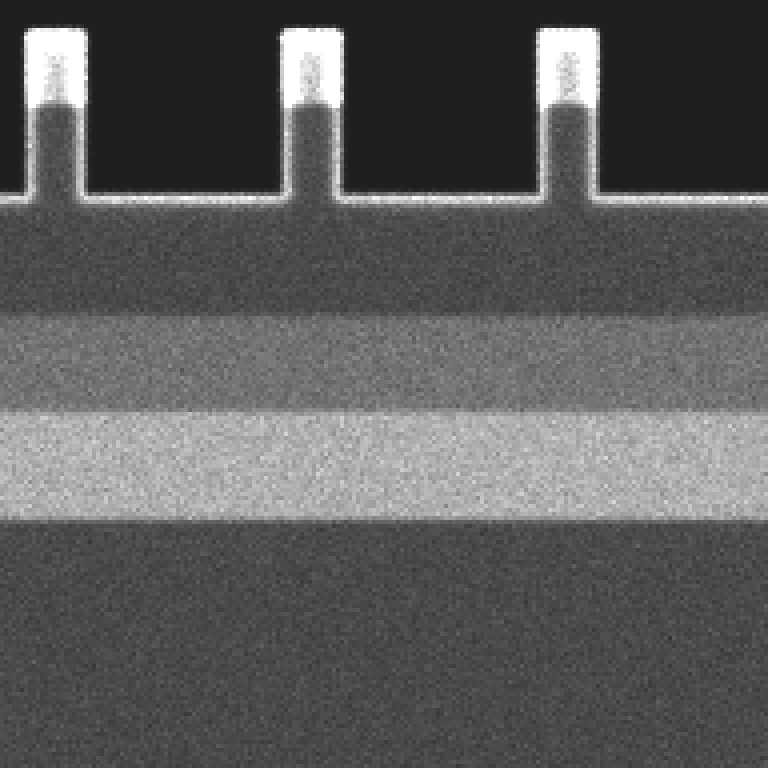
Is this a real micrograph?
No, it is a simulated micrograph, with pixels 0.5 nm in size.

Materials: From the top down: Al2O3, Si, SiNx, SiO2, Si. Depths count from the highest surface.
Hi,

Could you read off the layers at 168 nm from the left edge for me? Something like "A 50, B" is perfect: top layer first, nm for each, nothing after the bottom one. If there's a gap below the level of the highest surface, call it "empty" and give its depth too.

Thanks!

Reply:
Al2O3 36, Si 106, SiNx 48, SiO2 54, Si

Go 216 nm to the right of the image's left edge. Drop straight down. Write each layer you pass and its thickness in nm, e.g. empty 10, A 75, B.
empty 82, Si 60, SiNx 48, SiO2 54, Si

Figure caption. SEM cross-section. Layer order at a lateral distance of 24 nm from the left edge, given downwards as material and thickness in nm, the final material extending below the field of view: Al2O3 36, Si 106, SiNx 48, SiO2 54, Si